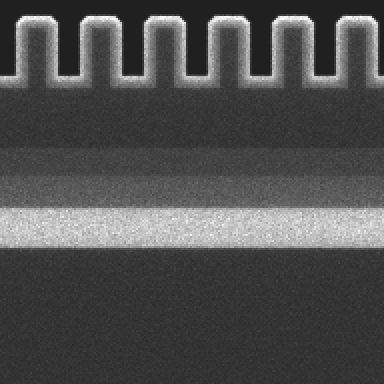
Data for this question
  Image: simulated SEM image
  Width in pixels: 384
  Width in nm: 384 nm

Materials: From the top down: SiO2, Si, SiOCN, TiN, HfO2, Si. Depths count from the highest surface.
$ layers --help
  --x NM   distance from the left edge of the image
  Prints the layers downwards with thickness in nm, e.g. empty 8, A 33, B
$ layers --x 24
SiO2 72, Si 60, SiOCN 28, TiN 32, HfO2 40, Si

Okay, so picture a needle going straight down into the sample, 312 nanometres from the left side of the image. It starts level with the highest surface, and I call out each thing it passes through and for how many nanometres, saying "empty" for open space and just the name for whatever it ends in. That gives empty 6, SiO2 66, Si 60, SiOCN 28, TiN 32, HfO2 40, Si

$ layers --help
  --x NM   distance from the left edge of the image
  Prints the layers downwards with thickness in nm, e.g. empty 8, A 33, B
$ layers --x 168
SiO2 12, Si 120, SiOCN 28, TiN 32, HfO2 40, Si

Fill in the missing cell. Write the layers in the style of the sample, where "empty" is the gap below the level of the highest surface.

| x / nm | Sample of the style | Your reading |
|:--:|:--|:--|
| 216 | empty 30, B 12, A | SiO2 72, Si 60, SiOCN 28, TiN 32, HfO2 40, Si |